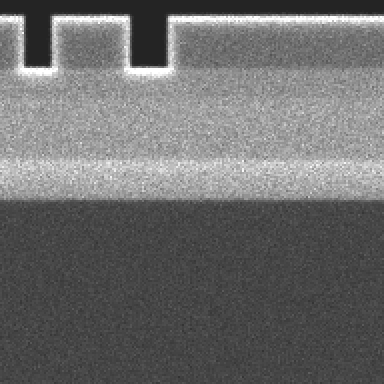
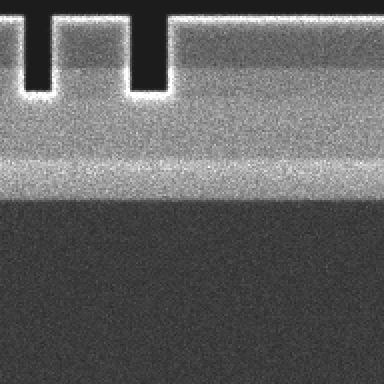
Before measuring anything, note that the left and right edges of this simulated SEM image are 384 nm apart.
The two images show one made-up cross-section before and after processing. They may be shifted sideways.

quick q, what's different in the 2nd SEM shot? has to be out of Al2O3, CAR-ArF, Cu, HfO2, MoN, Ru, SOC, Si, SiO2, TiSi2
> SiO2 removed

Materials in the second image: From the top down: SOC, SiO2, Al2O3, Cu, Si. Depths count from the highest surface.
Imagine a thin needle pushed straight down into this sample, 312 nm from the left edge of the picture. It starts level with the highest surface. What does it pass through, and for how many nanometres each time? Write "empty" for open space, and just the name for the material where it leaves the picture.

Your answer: SOC 52, SiO2 30, Al2O3 62, Cu 40, Si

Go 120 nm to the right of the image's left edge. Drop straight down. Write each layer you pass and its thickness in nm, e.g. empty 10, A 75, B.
SOC 52, SiO2 30, Al2O3 62, Cu 40, Si